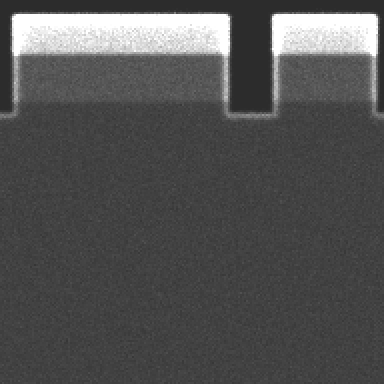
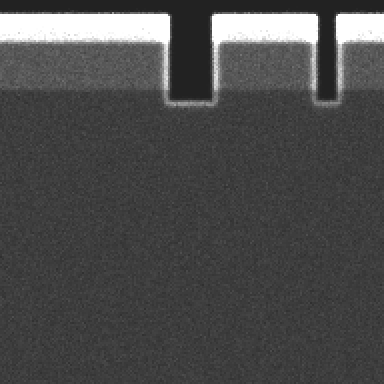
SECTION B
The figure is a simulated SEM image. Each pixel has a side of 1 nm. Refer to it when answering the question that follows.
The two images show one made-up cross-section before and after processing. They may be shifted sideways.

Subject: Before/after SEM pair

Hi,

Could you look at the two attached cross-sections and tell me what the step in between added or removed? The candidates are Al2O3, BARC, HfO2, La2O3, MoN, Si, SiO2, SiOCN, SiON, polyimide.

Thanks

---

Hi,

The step removed HfO2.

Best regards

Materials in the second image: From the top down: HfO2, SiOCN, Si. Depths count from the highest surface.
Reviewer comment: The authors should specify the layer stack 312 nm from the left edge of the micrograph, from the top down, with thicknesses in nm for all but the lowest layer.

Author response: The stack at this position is HfO2 26, SiOCN 48, Si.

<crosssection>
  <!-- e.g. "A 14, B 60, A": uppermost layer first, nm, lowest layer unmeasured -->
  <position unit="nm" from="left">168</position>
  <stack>empty 86, Si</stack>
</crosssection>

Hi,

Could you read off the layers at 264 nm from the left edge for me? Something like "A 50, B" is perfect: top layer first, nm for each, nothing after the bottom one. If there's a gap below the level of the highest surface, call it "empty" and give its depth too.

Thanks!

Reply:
HfO2 26, SiOCN 48, Si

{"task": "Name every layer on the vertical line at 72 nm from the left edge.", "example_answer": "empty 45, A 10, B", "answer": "HfO2 26, SiOCN 48, Si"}